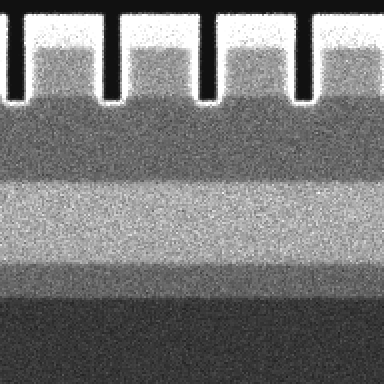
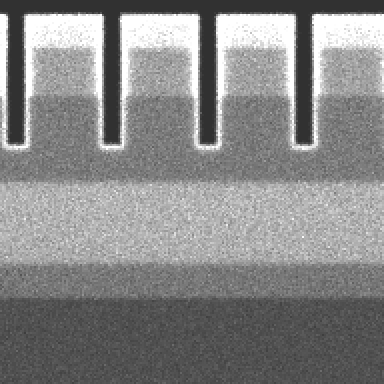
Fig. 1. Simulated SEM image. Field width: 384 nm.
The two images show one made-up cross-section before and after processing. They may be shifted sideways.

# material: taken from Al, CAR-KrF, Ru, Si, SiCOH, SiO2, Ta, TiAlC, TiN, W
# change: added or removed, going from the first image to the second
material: TiN
change: removed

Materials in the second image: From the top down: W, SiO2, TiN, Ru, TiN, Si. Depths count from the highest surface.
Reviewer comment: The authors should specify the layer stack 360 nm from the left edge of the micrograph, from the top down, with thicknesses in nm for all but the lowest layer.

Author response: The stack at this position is W 32, SiO2 48, TiN 86, Ru 82, TiN 34, Si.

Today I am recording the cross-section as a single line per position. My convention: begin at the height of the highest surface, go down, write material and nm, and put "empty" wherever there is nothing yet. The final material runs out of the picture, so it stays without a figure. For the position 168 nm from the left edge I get W 32, SiO2 48, TiN 86, Ru 82, TiN 34, Si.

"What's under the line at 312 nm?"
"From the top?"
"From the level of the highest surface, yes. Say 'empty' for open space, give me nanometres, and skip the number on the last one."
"empty 130, TiN 36, Ru 82, TiN 34, Si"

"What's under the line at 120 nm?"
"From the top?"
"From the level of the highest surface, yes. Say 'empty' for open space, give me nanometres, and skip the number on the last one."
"empty 130, TiN 36, Ru 82, TiN 34, Si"